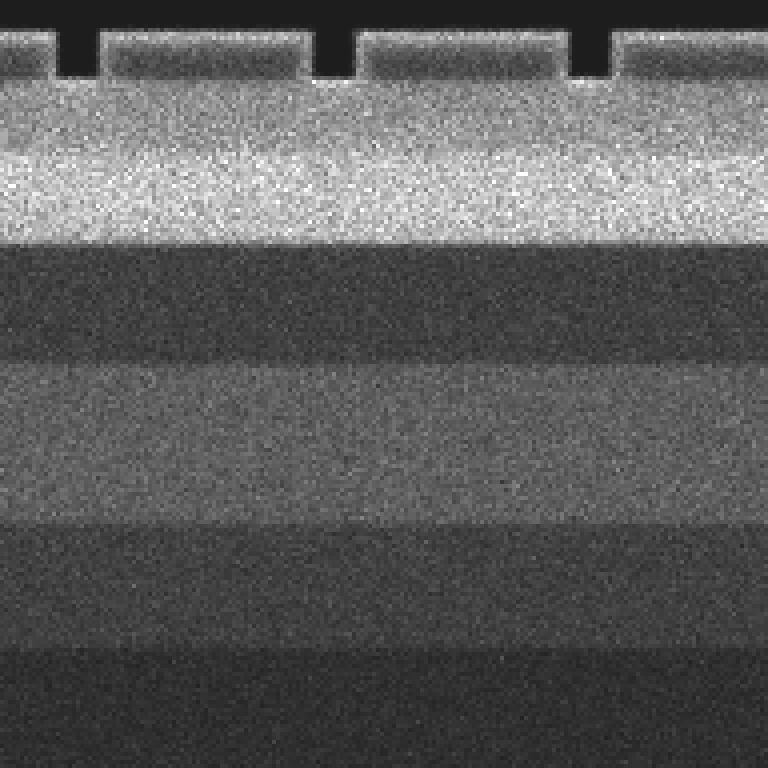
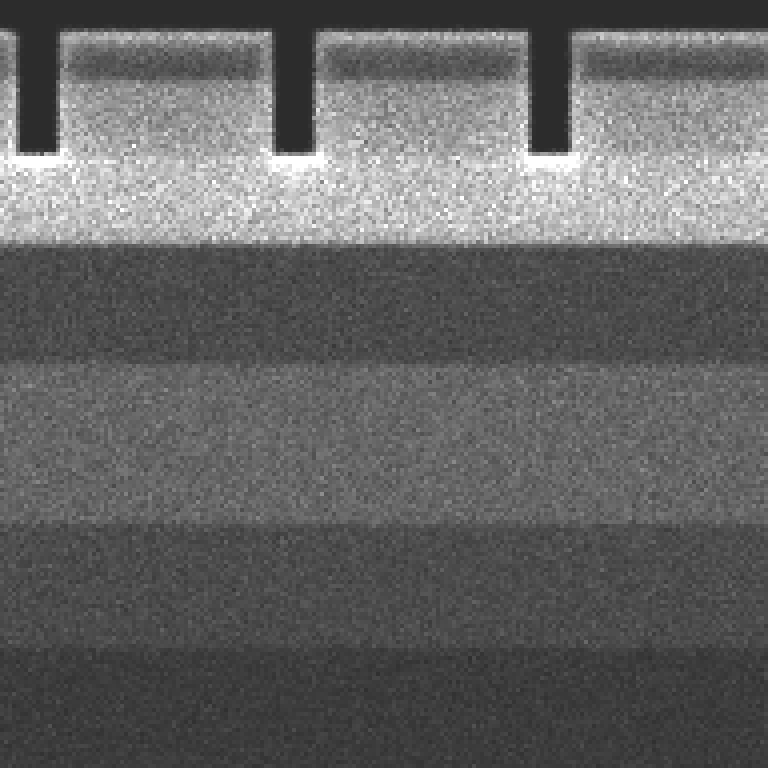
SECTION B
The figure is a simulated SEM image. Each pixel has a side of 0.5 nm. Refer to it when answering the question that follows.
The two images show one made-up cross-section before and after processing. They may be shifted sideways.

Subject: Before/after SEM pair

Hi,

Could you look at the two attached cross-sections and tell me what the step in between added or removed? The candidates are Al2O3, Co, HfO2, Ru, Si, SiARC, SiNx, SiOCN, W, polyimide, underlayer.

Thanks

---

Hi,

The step removed W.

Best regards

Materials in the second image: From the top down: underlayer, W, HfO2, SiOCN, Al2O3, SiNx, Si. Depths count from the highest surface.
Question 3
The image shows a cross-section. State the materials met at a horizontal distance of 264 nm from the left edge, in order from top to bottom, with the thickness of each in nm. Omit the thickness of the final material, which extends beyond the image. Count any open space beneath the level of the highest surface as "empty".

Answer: empty 62, HfO2 44, SiOCN 60, Al2O3 80, SiNx 62, Si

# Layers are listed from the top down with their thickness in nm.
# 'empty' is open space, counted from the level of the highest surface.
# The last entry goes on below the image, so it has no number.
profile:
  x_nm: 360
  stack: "underlayer 24, W 38, HfO2 44, SiOCN 60, Al2O3 80, SiNx 62, Si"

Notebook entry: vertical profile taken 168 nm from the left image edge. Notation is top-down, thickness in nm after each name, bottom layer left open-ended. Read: underlayer 24, W 38, HfO2 44, SiOCN 60, Al2O3 80, SiNx 62, Si